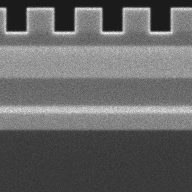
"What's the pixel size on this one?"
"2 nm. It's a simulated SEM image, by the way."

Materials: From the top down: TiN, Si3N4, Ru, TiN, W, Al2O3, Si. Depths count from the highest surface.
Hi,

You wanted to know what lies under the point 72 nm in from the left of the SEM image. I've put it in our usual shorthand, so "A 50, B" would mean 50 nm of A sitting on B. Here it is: TiN 48, Si3N4 28, Ru 64, TiN 56, W 14, Al2O3 34, Si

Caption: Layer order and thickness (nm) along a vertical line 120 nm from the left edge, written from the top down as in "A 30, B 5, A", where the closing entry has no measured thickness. empty 48, Si3N4 28, Ru 64, TiN 56, W 14, Al2O3 34, Si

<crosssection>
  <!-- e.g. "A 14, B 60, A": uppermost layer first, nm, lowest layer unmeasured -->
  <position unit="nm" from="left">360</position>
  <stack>TiN 48, Si3N4 28, Ru 64, TiN 56, W 14, Al2O3 34, Si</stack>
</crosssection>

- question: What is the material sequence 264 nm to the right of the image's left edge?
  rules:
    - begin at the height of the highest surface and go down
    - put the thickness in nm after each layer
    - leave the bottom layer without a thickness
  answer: TiN 48, Si3N4 28, Ru 64, TiN 56, W 14, Al2O3 34, Si